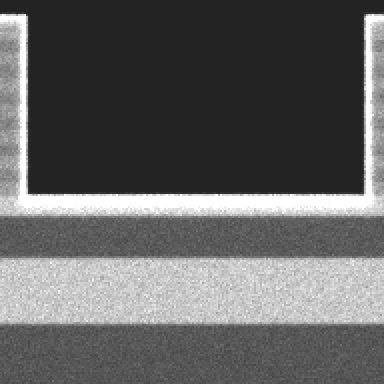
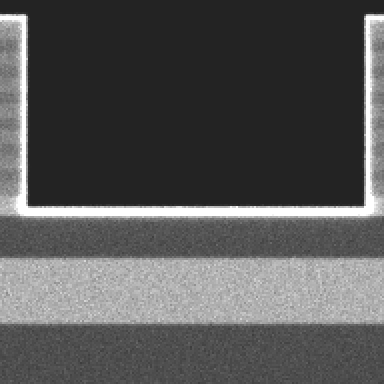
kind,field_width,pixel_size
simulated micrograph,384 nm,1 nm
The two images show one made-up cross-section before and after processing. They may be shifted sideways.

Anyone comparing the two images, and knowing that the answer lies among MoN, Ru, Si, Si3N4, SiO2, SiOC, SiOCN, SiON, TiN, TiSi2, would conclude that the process removed SiO2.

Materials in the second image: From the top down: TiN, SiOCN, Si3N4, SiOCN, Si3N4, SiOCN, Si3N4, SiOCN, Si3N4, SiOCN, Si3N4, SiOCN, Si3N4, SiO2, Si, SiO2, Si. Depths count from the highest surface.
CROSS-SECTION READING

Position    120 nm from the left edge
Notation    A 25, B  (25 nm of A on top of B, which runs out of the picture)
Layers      empty 192, SiO2 8, Si 42, SiO2 66, Si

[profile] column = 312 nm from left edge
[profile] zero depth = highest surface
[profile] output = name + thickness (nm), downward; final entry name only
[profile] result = empty 192, SiO2 8, Si 42, SiO2 66, Si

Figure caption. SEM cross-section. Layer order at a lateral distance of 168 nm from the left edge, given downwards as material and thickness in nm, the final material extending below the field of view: empty 192, SiO2 8, Si 42, SiO2 66, Si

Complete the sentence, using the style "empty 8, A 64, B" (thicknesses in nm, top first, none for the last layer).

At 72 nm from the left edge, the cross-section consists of empty 192, SiO2 8, Si 42, SiO2 66, Si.